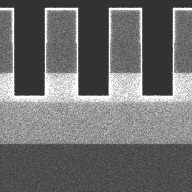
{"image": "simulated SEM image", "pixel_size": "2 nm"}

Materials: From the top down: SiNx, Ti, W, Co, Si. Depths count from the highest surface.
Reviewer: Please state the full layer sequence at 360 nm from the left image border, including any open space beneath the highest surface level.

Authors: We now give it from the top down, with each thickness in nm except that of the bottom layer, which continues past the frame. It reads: SiNx 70, Ti 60, W 58, Co 84, Si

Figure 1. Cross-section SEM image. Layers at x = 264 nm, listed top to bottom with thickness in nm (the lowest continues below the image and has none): SiNx 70, Ti 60, W 58, Co 84, Si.